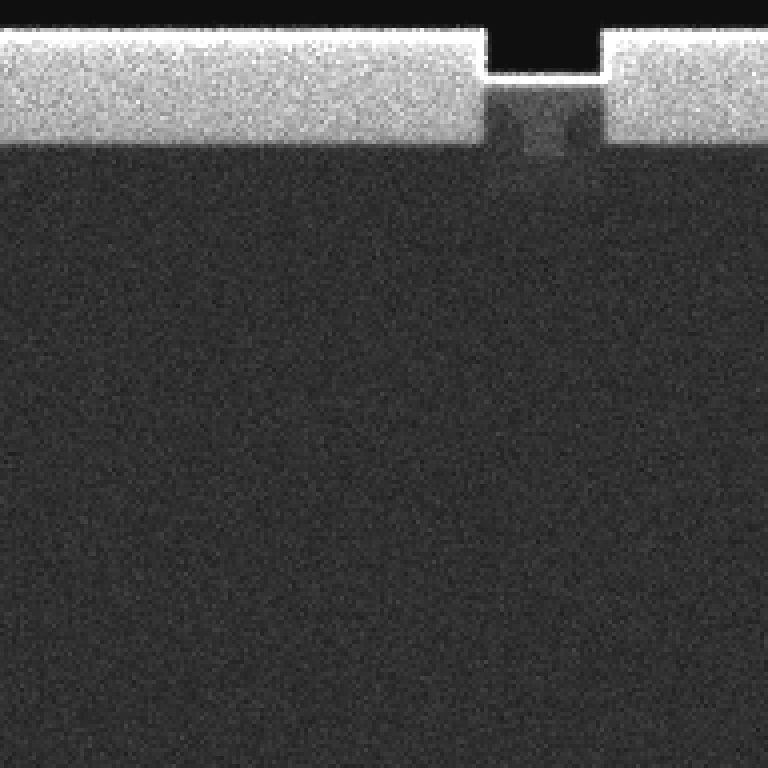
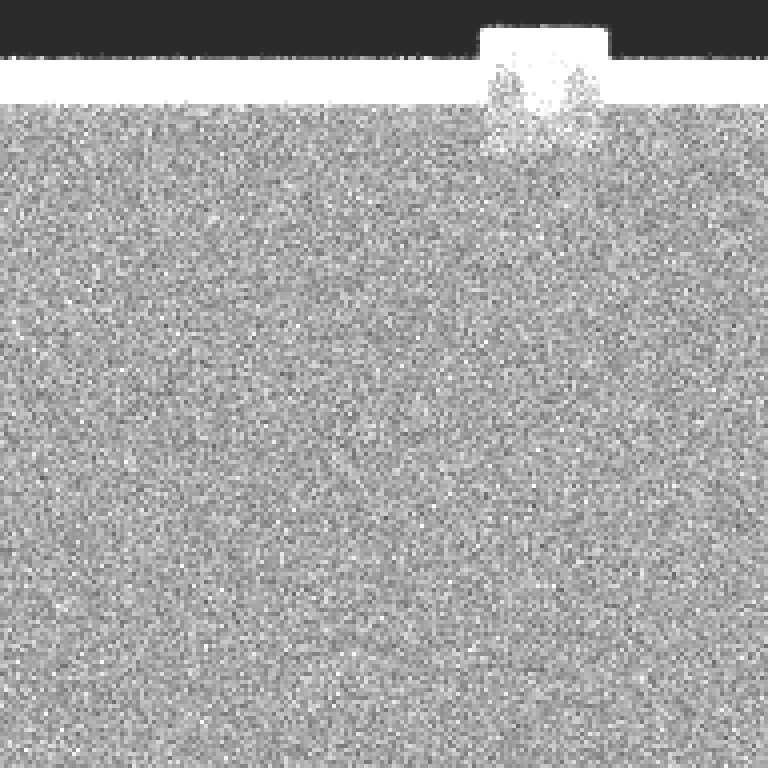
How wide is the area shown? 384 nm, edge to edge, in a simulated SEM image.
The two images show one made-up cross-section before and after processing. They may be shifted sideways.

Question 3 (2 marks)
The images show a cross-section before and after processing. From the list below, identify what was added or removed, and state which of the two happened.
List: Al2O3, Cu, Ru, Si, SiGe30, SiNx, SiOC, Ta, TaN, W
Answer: W was removed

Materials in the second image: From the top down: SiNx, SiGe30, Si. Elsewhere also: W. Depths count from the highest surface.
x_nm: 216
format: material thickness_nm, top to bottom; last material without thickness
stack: empty 16, W 18, Si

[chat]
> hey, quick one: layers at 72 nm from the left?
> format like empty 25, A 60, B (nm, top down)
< empty 16, W 18, Si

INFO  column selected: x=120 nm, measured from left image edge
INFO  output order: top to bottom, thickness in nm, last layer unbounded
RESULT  empty 16, W 18, Si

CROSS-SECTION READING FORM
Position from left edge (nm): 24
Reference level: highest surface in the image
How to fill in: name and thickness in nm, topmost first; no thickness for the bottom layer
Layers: empty 16, W 18, Si